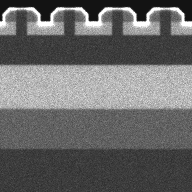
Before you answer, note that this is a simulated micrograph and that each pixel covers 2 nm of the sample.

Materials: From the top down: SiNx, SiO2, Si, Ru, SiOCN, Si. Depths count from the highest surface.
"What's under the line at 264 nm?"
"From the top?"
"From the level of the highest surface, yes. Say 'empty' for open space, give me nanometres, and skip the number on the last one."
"empty 6, SiNx 22, SiO2 26, Si 60, Ru 88, SiOCN 80, Si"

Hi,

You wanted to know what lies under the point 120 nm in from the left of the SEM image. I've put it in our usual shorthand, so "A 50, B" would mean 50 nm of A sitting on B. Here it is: SiNx 28, SiO2 26, Si 60, Ru 88, SiOCN 80, Si